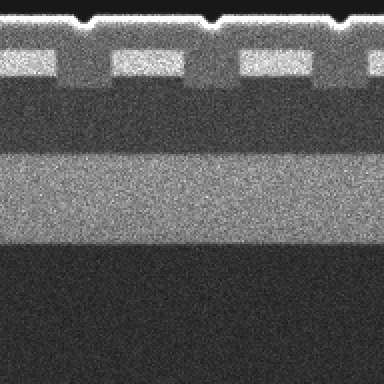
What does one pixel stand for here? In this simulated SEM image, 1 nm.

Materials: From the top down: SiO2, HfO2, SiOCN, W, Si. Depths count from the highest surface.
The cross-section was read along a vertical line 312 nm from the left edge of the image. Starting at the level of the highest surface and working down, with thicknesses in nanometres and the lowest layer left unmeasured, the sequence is SiO2 72, SiOCN 66, W 90, Si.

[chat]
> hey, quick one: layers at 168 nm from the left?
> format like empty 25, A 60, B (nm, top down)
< SiO2 34, HfO2 26, SiOCN 78, W 90, Si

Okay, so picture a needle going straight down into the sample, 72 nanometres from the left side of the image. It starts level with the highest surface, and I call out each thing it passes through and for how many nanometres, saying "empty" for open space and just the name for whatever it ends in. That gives SiO2 72, SiOCN 66, W 90, Si